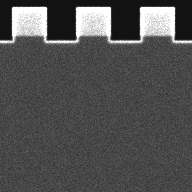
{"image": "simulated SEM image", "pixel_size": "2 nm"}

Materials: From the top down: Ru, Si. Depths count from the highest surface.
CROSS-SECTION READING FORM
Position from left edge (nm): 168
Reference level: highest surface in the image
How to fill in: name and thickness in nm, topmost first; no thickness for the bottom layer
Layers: Ru 56, Si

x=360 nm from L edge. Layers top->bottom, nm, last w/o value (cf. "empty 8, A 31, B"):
empty 66, Si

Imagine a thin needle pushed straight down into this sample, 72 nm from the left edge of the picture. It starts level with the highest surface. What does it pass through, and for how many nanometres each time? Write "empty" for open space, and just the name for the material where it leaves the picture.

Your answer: Ru 56, Si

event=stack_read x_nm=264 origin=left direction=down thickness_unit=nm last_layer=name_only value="empty 66, Si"